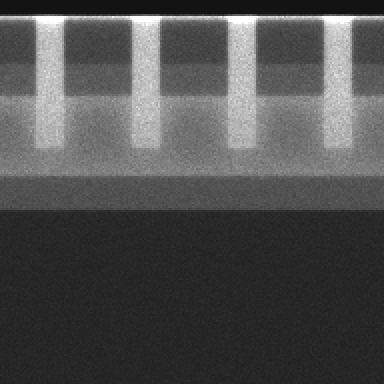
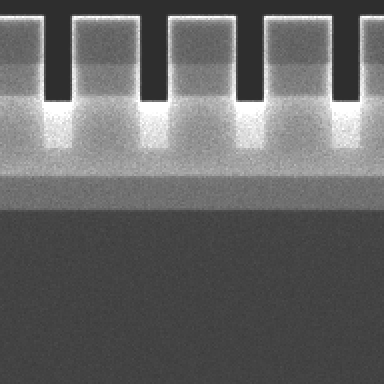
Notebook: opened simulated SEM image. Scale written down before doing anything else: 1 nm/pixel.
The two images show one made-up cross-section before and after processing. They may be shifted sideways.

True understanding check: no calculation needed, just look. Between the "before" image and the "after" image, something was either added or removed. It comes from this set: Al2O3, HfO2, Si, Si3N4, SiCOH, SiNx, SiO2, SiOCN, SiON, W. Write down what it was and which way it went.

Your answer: HfO2 (removed)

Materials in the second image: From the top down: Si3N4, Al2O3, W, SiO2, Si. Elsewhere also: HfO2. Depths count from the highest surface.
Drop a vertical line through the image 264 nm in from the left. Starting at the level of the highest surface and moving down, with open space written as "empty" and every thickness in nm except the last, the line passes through Si3N4 48, Al2O3 32, W 80, SiO2 34, Si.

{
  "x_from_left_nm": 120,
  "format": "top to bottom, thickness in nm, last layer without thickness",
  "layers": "Si3N4 48, Al2O3 32, W 80, SiO2 34, Si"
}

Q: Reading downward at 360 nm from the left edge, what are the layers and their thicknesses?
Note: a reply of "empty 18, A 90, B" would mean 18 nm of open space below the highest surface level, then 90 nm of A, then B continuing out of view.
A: Si3N4 48, Al2O3 32, W 80, SiO2 34, Si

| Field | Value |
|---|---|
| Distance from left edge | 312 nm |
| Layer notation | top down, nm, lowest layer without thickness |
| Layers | Si3N4 48, Al2O3 32, W 80, SiO2 34, Si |